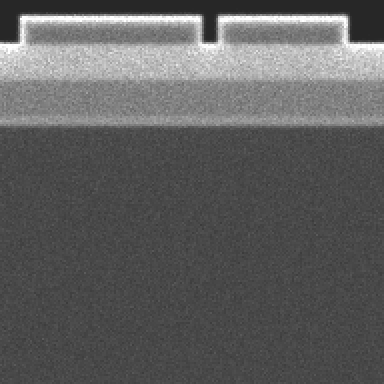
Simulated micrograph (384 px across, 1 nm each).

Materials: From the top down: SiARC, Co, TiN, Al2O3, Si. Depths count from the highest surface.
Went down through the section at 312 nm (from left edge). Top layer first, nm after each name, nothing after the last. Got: SiARC 28, Co 36, TiN 36, Al2O3 10, Si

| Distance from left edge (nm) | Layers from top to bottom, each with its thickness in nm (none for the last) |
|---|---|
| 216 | empty 28, Co 36, TiN 36, Al2O3 10, Si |